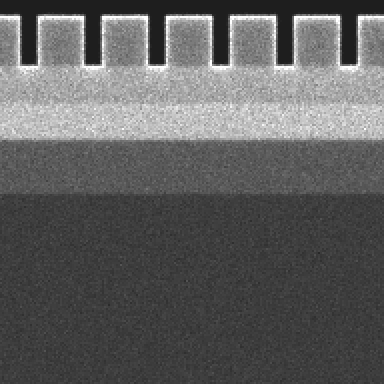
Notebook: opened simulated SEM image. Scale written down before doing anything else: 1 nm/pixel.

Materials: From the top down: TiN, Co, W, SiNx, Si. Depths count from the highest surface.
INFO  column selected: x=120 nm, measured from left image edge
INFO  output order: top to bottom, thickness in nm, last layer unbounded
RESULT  TiN 50, Co 38, W 36, SiNx 54, Si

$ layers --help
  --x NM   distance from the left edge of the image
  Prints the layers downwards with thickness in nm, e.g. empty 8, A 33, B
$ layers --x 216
empty 50, Co 38, W 36, SiNx 54, Si